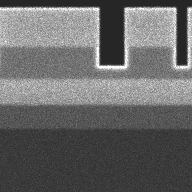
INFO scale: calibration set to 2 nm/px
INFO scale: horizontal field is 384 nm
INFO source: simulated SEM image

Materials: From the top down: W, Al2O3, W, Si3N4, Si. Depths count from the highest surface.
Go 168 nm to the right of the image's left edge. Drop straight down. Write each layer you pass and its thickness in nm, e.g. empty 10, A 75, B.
W 78, Al2O3 64, W 52, Si3N4 48, Si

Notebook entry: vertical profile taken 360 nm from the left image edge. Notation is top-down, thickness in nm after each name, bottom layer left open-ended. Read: empty 116, Al2O3 26, W 52, Si3N4 48, Si